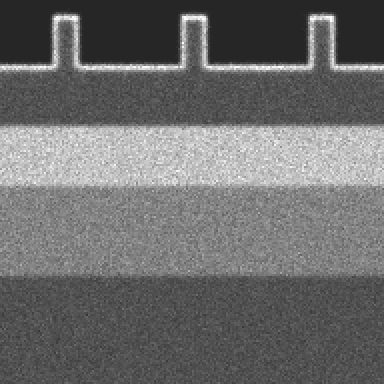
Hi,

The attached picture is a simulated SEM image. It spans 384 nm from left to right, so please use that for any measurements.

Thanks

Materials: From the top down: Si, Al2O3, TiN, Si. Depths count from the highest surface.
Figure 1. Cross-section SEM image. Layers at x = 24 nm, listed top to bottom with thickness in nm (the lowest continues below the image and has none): empty 50, Si 60, Al2O3 60, TiN 90, Si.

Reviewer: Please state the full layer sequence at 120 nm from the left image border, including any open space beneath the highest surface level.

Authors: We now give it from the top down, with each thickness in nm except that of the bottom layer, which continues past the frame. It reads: empty 50, Si 60, Al2O3 60, TiN 90, Si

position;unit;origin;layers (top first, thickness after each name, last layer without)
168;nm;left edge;empty 50, Si 60, Al2O3 60, TiN 90, Si